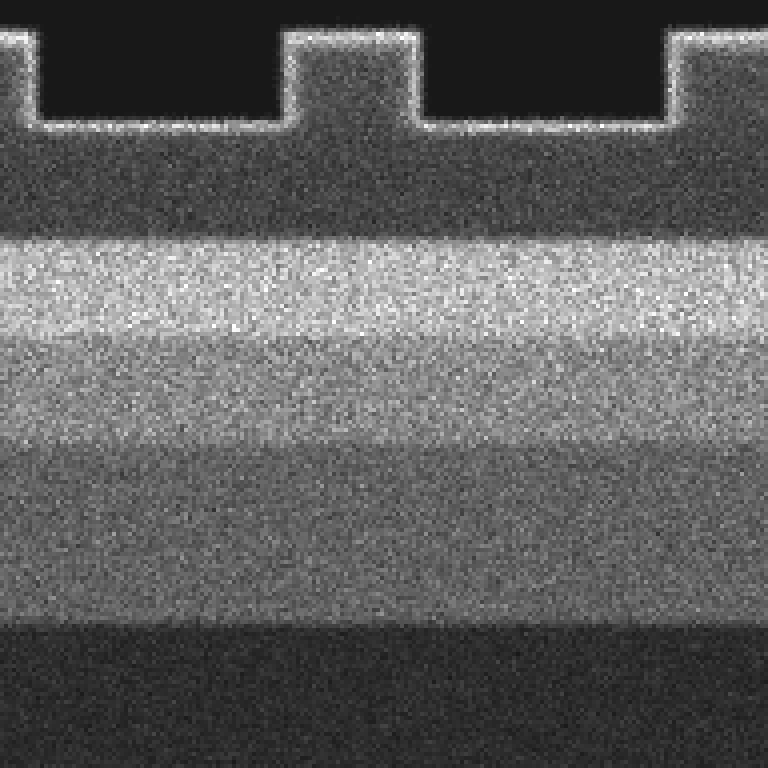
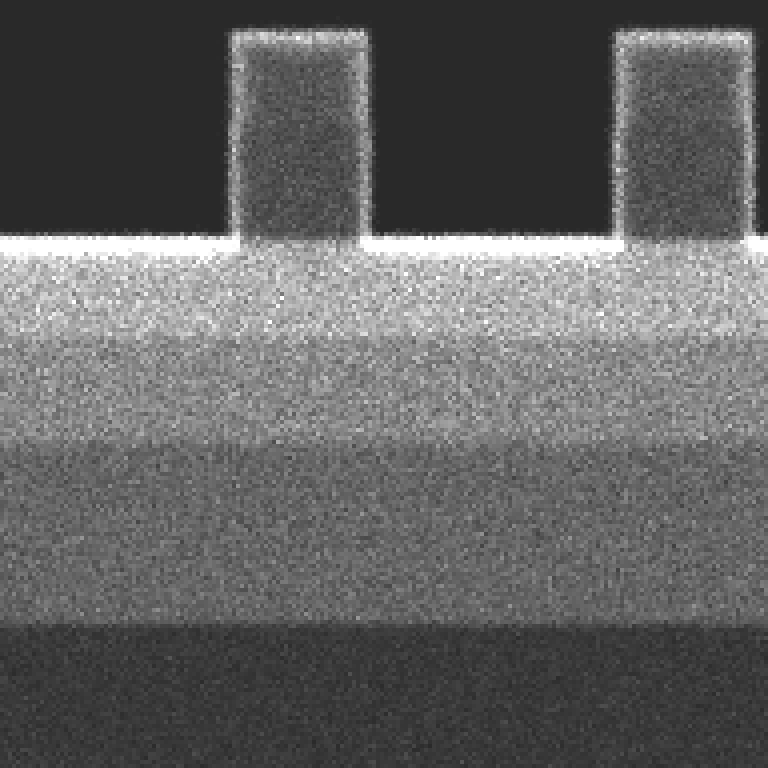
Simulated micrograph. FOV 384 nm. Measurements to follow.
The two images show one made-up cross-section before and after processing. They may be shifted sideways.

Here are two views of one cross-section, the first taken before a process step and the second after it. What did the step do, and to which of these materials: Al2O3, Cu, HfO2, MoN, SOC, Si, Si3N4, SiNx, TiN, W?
It removed TiN.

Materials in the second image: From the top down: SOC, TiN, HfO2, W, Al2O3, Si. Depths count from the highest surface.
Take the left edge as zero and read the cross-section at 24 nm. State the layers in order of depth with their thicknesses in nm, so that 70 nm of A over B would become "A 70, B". empty 104, HfO2 48, W 54, Al2O3 90, Si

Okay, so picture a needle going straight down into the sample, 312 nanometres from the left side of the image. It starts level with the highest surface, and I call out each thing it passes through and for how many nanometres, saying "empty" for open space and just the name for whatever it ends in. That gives SOC 46, TiN 58, HfO2 48, W 54, Al2O3 90, Si